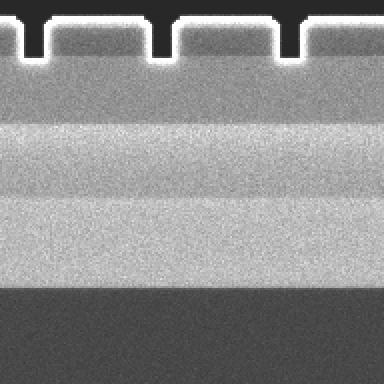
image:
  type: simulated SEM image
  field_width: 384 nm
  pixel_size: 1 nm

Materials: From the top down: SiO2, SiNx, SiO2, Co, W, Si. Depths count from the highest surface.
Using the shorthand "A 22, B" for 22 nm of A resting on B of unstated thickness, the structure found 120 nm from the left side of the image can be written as SiO2 12, SiNx 28, SiO2 68, Co 74, W 90, Si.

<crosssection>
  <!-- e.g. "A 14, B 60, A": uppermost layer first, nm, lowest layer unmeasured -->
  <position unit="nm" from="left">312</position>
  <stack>SiO2 12, SiNx 28, SiO2 68, Co 74, W 90, Si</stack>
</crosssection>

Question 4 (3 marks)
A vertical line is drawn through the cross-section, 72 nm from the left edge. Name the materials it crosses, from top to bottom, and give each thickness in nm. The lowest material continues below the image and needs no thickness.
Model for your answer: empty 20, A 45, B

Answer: SiO2 12, SiNx 28, SiO2 68, Co 74, W 90, Si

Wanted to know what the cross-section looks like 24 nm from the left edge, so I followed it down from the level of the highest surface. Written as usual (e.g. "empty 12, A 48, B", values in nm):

empty 42, SiO2 66, Co 74, W 90, Si